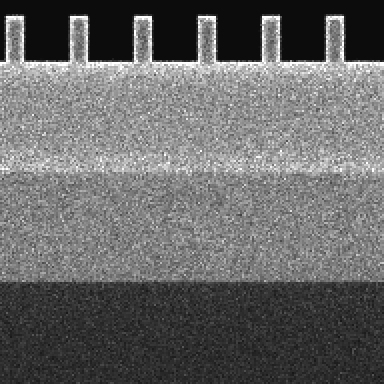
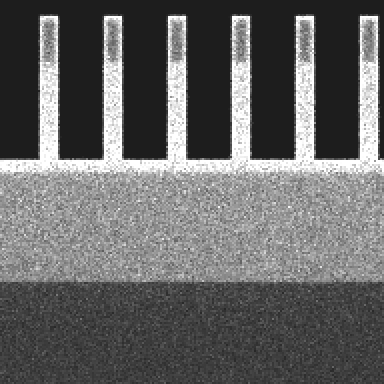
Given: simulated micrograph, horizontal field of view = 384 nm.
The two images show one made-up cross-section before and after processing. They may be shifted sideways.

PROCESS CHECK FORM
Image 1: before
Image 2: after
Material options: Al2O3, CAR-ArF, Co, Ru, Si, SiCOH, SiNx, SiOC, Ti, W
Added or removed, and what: removed, W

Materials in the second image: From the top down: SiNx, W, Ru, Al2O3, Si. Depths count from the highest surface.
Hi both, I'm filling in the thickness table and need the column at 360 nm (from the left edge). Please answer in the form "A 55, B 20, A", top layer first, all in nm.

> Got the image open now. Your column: SiNx 46, W 98, Ru 12, Al2O3 110, Si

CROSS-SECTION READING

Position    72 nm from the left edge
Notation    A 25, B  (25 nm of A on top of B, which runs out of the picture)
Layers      empty 144, Ru 12, Al2O3 110, Si